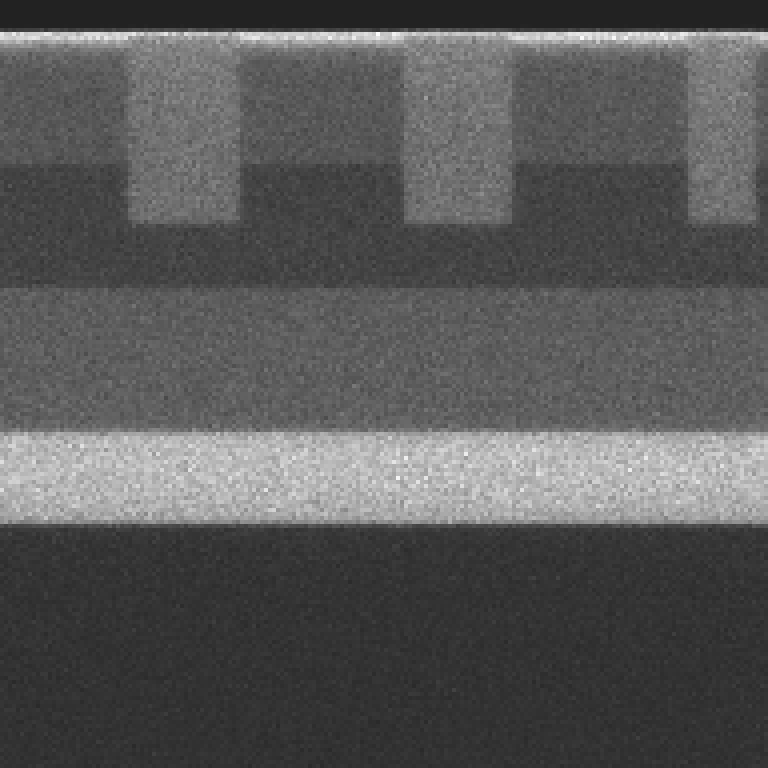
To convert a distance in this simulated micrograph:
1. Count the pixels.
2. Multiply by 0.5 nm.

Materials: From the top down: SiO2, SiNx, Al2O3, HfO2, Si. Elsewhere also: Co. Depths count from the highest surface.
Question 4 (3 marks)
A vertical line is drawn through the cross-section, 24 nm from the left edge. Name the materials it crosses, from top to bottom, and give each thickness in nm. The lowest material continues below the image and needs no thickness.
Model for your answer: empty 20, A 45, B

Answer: SiO2 66, SiNx 62, Al2O3 72, HfO2 46, Si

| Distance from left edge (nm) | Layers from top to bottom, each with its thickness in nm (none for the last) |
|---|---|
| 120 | SiO2 66, SiNx 62, Al2O3 72, HfO2 46, Si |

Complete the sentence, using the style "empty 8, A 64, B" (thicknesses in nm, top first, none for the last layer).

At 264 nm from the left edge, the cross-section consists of SiO2 66, SiNx 62, Al2O3 72, HfO2 46, Si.